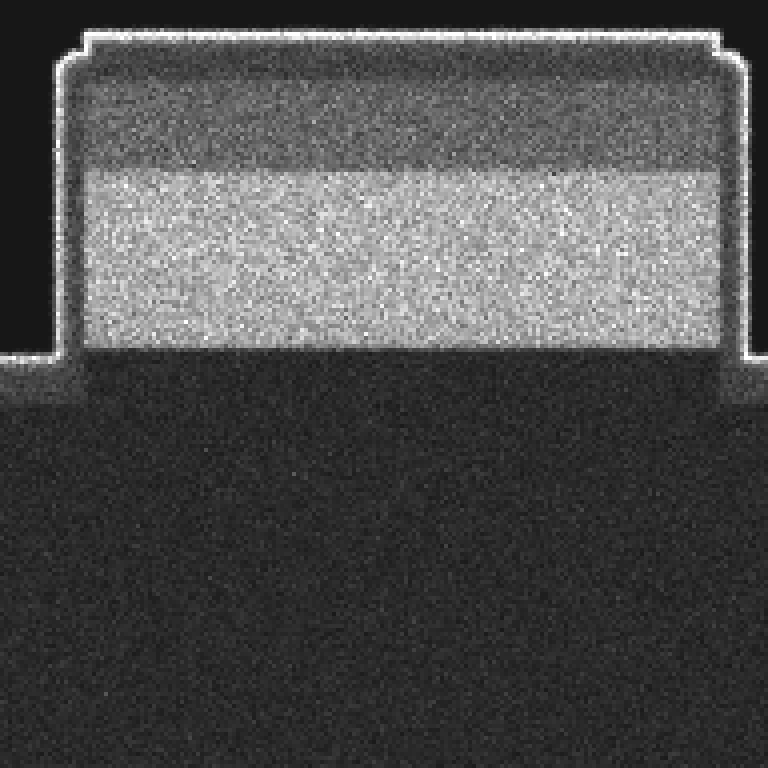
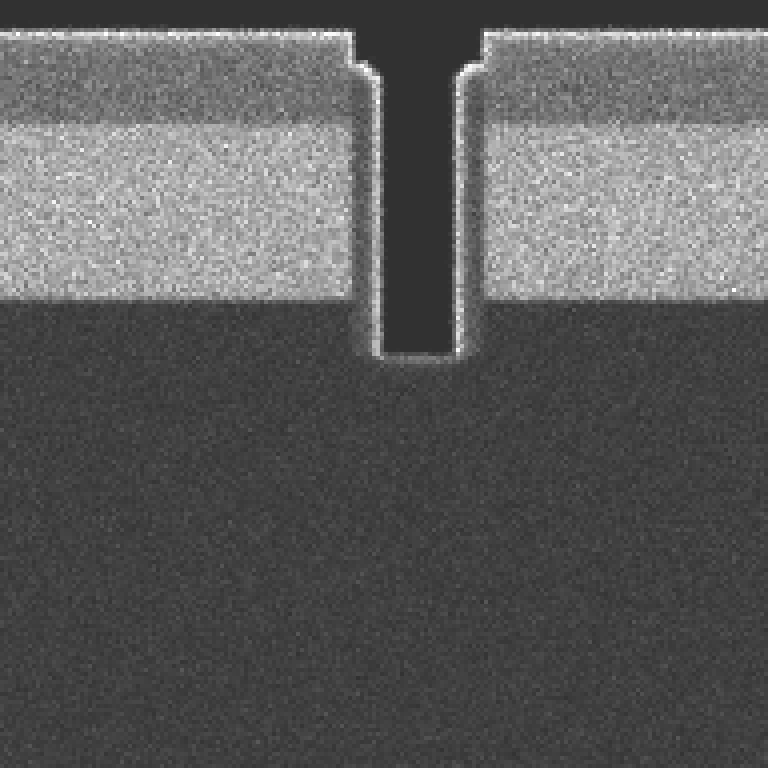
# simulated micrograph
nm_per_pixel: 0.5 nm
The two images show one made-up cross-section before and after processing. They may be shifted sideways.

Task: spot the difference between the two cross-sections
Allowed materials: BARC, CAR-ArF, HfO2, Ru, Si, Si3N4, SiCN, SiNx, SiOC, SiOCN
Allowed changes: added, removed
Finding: removed Si3N4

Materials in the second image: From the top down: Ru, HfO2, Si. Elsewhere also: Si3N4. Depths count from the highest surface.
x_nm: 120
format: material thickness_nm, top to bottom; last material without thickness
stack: Ru 46, HfO2 88, Si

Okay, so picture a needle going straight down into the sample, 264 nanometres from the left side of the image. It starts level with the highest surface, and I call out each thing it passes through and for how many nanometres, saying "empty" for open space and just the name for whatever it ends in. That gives Ru 46, HfO2 88, Si